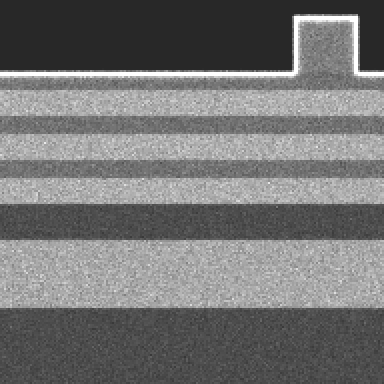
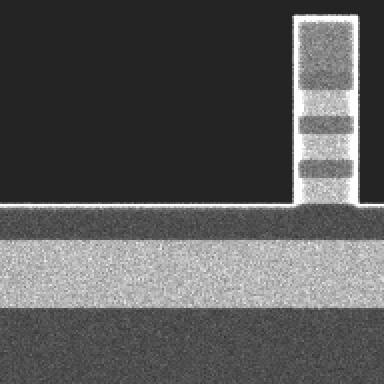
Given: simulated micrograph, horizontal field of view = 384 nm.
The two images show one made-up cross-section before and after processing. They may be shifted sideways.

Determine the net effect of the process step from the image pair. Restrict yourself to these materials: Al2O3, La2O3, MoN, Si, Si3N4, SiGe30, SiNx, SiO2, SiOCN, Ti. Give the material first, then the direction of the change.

Al2O3 and SiNx: removed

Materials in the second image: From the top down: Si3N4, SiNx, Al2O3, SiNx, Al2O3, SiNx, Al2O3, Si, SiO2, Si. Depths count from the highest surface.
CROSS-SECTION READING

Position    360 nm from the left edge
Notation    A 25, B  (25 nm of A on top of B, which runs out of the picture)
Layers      empty 188, Si 36, SiO2 68, Si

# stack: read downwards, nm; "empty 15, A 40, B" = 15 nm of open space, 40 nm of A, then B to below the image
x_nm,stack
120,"empty 188, Si 36, SiO2 68, Si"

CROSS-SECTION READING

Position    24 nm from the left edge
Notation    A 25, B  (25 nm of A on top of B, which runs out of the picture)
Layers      empty 188, Si 36, SiO2 68, Si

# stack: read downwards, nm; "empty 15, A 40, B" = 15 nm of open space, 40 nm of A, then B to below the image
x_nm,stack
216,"empty 188, Si 36, SiO2 68, Si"